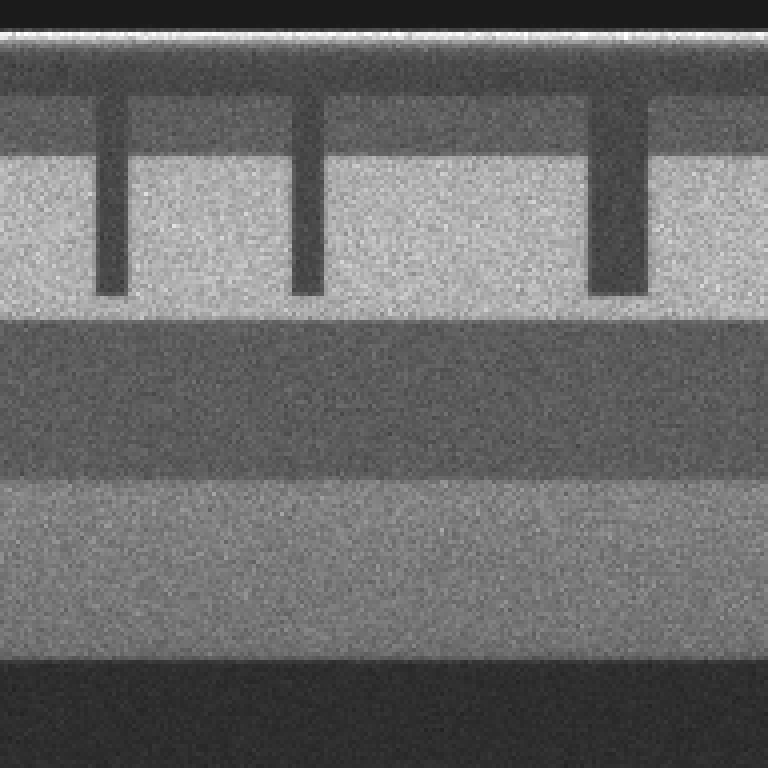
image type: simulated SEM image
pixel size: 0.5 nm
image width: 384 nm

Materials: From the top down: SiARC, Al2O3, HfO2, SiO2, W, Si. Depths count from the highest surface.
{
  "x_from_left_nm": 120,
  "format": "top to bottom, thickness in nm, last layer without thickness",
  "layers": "SiARC 32, Al2O3 30, HfO2 82, SiO2 80, W 90, Si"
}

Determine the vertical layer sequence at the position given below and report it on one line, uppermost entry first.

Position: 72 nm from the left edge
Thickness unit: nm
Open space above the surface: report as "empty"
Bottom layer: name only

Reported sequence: SiARC 32, Al2O3 30, HfO2 82, SiO2 80, W 90, Si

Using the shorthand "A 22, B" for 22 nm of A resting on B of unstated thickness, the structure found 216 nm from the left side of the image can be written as SiARC 32, Al2O3 30, HfO2 82, SiO2 80, W 90, Si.